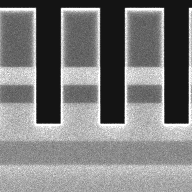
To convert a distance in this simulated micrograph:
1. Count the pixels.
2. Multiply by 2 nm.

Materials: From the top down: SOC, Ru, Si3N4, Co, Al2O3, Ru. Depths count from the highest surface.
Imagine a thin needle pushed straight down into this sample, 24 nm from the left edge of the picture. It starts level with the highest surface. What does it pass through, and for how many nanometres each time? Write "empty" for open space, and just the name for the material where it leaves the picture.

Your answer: SOC 118, Ru 36, Si3N4 36, Co 76, Al2O3 48, Ru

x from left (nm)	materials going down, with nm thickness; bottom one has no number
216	empty 232, Co 34, Al2O3 48, Ru